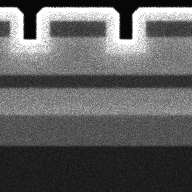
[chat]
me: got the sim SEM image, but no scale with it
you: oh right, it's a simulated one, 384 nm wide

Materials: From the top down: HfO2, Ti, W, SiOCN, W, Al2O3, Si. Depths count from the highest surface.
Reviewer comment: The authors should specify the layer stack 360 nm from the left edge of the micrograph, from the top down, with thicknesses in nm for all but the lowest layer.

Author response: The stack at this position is HfO2 26, Ti 32, W 76, SiOCN 26, W 54, Al2O3 62, Si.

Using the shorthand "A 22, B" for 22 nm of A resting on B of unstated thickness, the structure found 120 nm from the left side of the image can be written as HfO2 26, Ti 32, W 76, SiOCN 26, W 54, Al2O3 62, Si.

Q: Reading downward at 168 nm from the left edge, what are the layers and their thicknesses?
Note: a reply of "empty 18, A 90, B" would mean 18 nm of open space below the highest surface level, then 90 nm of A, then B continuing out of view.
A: HfO2 26, Ti 32, W 76, SiOCN 26, W 54, Al2O3 62, Si